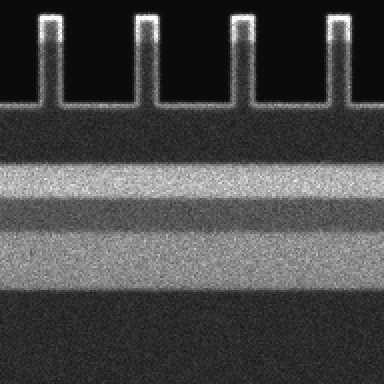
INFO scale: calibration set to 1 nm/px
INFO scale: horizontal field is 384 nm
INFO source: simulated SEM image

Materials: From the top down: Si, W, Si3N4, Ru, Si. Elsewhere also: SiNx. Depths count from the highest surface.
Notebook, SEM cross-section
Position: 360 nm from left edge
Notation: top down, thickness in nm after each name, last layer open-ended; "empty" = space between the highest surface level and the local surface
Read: empty 88, Si 60, W 34, Si3N4 34, Ru 58, Si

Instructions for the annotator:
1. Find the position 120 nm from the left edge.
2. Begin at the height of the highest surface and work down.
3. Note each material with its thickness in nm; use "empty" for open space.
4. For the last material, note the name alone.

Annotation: empty 88, Si 60, W 34, Si3N4 34, Ru 58, Si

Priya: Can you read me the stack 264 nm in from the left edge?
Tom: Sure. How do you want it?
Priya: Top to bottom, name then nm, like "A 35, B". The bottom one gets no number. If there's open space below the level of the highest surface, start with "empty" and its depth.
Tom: empty 88, Si 60, W 34, Si3N4 34, Ru 58, Si